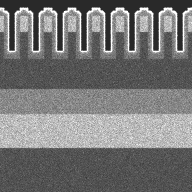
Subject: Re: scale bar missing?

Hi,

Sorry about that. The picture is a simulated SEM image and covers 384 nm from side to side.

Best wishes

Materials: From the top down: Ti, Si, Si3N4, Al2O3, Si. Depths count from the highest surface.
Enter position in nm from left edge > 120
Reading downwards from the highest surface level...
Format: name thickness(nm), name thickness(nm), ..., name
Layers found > empty 86, Ti 16, Si 60, Si3N4 50, Al2O3 68, Si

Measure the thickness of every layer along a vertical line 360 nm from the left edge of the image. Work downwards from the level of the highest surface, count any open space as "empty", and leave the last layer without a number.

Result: empty 86, Ti 16, Si 60, Si3N4 50, Al2O3 68, Si